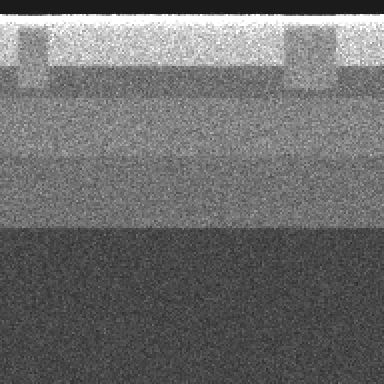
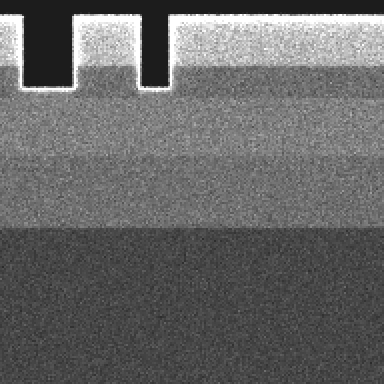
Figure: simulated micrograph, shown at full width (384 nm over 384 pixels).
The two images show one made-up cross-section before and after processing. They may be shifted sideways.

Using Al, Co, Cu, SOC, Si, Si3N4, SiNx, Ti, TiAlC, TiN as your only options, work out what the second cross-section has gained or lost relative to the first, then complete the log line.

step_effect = removed SOC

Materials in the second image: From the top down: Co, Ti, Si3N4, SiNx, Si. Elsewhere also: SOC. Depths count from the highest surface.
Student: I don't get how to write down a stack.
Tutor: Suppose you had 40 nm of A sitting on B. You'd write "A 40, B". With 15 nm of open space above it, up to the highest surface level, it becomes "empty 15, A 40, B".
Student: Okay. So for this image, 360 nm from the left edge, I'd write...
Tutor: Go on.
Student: Co 50, Ti 32, Si3N4 58, SiNx 72, Si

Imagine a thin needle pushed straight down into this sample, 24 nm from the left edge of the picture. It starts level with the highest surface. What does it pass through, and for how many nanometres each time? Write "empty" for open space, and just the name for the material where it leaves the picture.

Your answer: empty 72, Ti 10, Si3N4 58, SiNx 72, Si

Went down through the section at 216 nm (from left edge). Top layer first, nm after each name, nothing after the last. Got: Co 50, Ti 32, Si3N4 58, SiNx 72, Si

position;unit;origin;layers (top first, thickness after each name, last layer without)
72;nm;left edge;empty 72, Ti 10, Si3N4 58, SiNx 72, Si